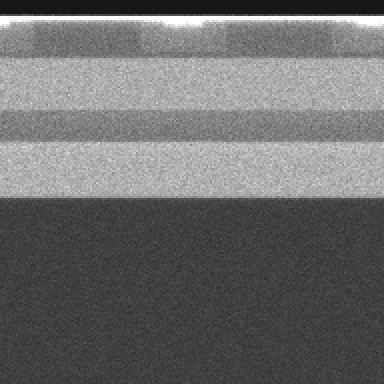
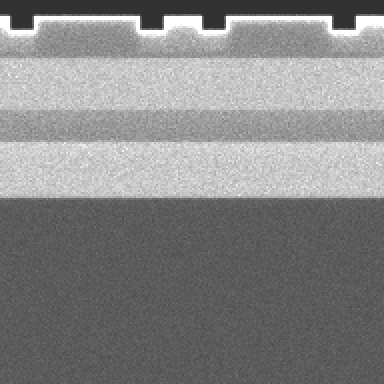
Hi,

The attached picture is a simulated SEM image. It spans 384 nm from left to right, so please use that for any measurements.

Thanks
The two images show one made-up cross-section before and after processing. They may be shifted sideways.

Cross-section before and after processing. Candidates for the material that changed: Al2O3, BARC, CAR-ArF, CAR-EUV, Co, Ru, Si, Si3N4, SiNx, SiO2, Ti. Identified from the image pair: Si3N4 (removed).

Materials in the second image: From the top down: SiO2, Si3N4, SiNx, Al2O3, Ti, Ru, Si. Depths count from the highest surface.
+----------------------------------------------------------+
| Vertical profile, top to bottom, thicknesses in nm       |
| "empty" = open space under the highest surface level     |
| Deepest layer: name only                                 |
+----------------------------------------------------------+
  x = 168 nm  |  SiO2 12, Si3N4 24, SiNx 6, Al2O3 52, Ti 32, Ru 56, Si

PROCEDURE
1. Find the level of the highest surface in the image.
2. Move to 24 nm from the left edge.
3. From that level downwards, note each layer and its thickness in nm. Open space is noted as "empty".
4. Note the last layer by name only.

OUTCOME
empty 14, Si3N4 22, SiNx 6, Al2O3 52, Ti 32, Ru 56, Si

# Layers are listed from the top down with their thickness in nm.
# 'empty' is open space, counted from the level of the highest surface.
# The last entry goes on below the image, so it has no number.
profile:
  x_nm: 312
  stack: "SiNx 42, Al2O3 52, Ti 32, Ru 56, Si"